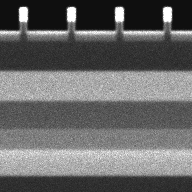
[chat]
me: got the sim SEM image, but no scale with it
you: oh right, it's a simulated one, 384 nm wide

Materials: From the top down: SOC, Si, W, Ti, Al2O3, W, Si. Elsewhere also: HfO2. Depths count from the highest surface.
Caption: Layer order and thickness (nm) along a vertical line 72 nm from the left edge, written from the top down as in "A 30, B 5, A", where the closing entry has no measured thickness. empty 46, SOC 20, Si 60, W 60, Ti 56, Al2O3 42, W 52, Si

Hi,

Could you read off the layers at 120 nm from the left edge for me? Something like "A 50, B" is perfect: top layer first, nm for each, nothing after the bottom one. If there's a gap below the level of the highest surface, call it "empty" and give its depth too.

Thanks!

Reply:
empty 46, SOC 20, Si 60, W 60, Ti 56, Al2O3 42, W 52, Si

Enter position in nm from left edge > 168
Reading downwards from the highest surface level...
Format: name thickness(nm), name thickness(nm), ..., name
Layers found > empty 46, SOC 20, Si 60, W 60, Ti 56, Al2O3 42, W 52, Si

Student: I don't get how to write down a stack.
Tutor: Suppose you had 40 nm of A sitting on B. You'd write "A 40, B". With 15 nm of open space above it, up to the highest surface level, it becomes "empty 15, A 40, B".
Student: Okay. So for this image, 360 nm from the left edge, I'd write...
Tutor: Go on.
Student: empty 46, SOC 20, Si 60, W 60, Ti 56, Al2O3 42, W 52, Si